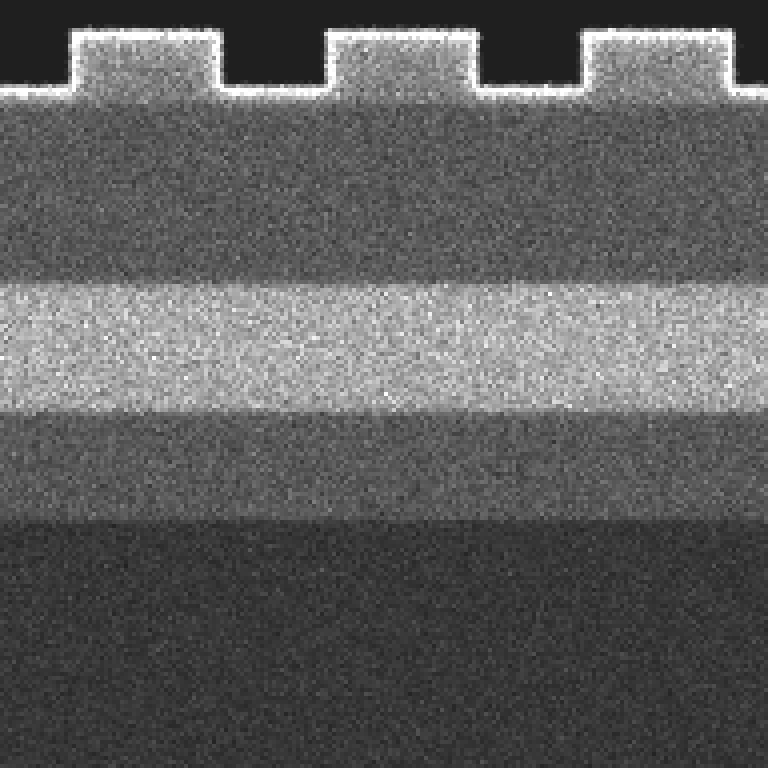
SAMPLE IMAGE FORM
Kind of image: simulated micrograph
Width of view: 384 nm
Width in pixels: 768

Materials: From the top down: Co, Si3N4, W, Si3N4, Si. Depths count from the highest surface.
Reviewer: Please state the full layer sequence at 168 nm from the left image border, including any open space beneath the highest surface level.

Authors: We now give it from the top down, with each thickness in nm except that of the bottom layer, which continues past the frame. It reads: Co 36, Si3N4 90, W 64, Si3N4 54, Si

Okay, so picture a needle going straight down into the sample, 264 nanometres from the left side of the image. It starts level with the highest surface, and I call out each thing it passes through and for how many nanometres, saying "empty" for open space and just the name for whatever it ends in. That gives empty 28, Co 8, Si3N4 90, W 64, Si3N4 54, Si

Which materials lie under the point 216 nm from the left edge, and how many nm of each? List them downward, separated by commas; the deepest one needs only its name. Co 36, Si3N4 90, W 64, Si3N4 54, Si